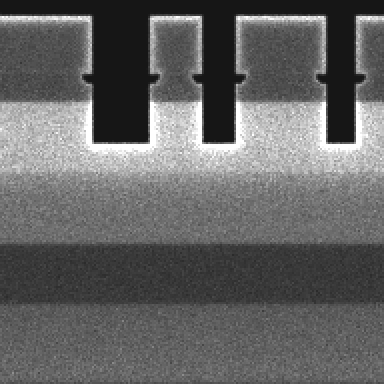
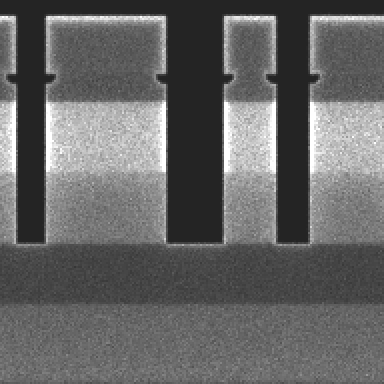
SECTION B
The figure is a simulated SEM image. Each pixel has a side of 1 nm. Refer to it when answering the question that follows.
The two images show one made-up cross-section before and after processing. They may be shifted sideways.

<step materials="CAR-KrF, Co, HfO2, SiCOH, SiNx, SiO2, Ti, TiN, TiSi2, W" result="removed HfO2 and W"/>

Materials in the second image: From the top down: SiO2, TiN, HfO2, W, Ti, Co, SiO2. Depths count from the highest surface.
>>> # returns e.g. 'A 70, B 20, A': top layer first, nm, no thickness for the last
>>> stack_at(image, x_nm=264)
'SiO2 58, TiN 28, HfO2 70, W 72, Ti 60, Co 78, SiO2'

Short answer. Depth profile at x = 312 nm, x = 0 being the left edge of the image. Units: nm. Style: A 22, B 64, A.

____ SiO2 58, empty 10, TiN 18, HfO2 70, W 72, Ti 60, Co 78, SiO2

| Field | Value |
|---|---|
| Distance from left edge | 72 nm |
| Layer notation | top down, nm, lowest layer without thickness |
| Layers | SiO2 58, TiN 28, HfO2 70, W 72, Ti 60, Co 78, SiO2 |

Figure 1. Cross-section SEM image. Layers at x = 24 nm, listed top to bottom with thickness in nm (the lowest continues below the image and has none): empty 228, Ti 60, Co 78, SiO2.